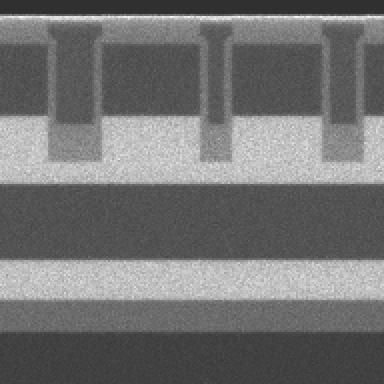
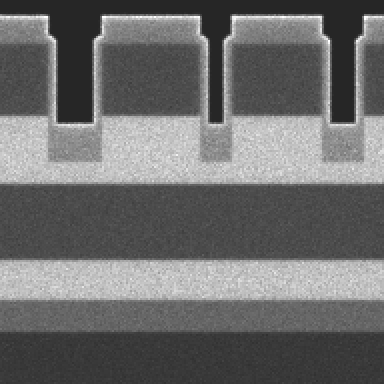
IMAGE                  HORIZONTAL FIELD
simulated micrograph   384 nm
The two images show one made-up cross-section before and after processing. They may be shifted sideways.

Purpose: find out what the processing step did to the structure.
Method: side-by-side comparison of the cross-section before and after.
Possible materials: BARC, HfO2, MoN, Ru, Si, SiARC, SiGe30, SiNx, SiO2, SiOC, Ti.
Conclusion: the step removed SiARC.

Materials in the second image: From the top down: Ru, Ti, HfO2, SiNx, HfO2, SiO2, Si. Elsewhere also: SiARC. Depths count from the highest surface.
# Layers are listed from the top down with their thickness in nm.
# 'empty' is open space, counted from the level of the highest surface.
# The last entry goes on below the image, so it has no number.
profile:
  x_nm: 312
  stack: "Ru 28, Ti 72, HfO2 68, SiNx 76, HfO2 40, SiO2 32, Si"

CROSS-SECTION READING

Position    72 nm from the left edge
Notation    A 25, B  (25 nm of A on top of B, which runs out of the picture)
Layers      empty 108, Ru 38, HfO2 22, SiNx 76, HfO2 40, SiO2 32, Si